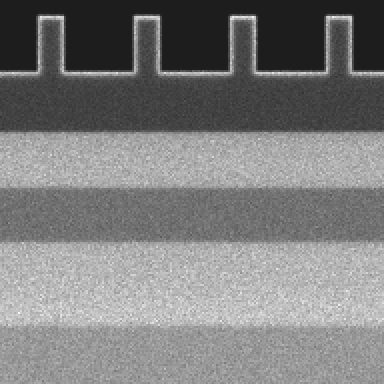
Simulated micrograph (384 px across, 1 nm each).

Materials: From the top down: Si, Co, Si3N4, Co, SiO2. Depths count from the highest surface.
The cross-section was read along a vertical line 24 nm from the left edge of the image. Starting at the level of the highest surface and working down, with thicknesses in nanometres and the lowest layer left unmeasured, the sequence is empty 56, Si 60, Co 56, Si3N4 54, Co 84, SiO2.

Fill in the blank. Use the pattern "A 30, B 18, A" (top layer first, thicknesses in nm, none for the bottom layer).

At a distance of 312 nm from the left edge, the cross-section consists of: empty 56, Si 60, Co 56, Si3N4 54, Co 84, SiO2